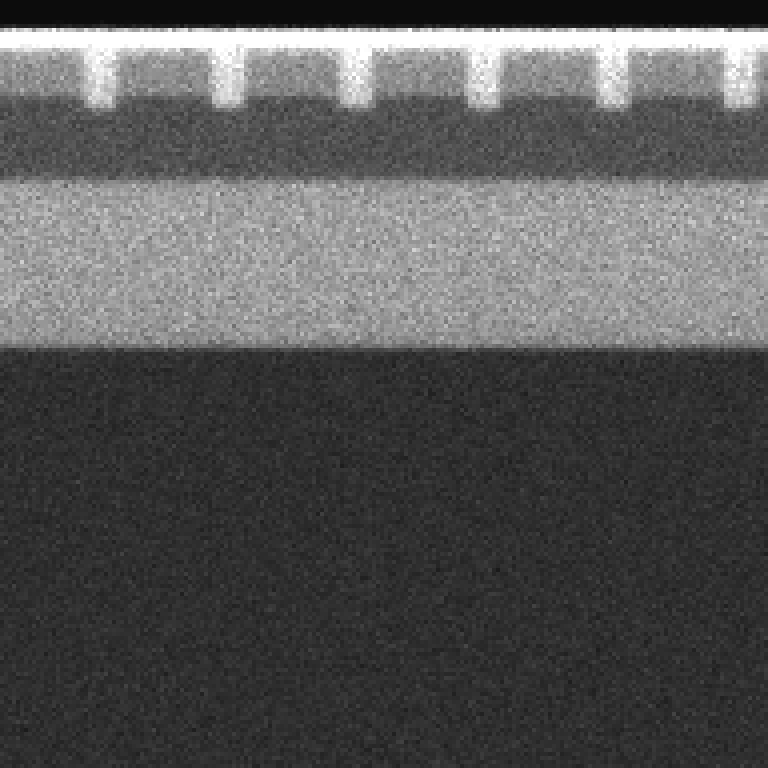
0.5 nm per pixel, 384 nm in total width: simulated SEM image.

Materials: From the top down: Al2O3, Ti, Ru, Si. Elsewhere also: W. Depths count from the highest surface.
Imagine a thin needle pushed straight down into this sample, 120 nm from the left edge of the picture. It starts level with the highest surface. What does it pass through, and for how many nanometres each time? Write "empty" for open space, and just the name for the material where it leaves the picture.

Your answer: W 38, Ti 36, Ru 84, Si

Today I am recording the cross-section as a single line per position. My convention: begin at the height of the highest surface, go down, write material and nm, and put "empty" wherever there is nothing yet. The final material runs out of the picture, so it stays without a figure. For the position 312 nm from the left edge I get W 38, Ti 36, Ru 84, Si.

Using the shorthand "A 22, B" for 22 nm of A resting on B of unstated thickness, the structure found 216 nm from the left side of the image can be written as Al2O3 32, Ti 42, Ru 84, Si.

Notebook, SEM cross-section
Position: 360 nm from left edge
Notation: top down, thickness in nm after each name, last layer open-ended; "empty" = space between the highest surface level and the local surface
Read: Al2O3 32, Ti 42, Ru 84, Si